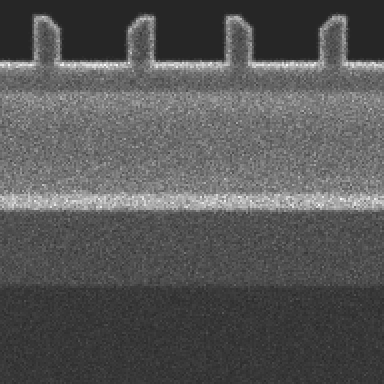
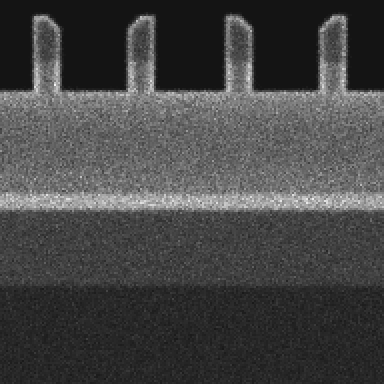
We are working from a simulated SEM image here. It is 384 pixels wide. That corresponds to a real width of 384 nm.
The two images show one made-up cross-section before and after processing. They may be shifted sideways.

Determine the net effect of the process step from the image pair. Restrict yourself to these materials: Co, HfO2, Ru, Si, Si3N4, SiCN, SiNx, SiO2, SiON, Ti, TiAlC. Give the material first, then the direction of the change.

SiO2: removed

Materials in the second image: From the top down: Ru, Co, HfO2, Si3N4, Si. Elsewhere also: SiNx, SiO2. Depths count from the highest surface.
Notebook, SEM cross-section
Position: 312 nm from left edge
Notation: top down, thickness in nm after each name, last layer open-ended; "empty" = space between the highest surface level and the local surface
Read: empty 76, Ru 92, Co 10, HfO2 16, Si3N4 76, Si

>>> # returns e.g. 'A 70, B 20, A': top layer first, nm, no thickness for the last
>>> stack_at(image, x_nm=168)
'empty 76, Ru 92, Co 10, HfO2 16, Si3N4 76, Si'